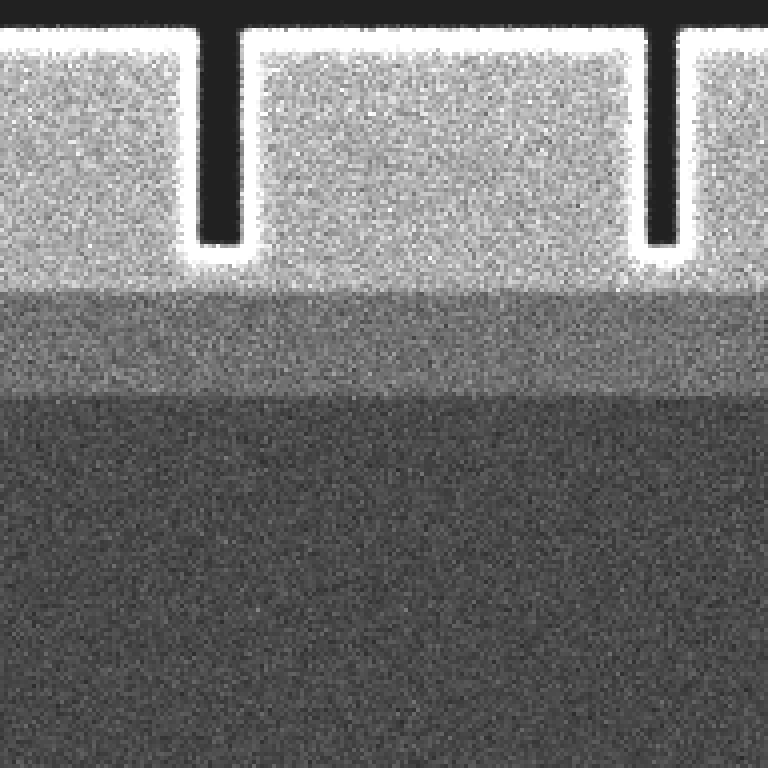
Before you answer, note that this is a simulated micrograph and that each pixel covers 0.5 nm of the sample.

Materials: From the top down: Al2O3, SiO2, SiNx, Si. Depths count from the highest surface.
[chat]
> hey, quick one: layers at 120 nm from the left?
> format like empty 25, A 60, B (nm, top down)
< empty 108, SiO2 22, SiNx 52, Si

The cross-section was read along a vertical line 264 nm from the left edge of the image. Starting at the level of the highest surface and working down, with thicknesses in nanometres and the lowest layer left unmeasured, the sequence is Al2O3 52, SiO2 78, SiNx 52, Si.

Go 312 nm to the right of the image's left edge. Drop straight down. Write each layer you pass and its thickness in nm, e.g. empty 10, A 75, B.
Al2O3 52, SiO2 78, SiNx 52, Si